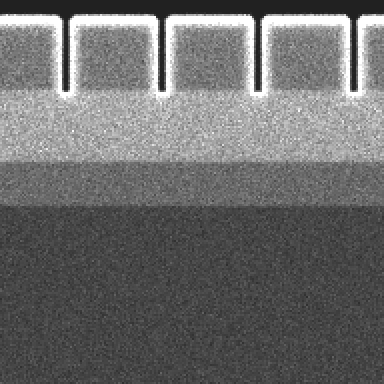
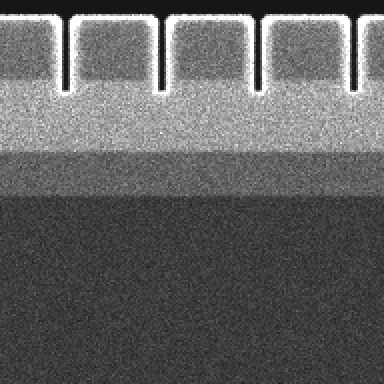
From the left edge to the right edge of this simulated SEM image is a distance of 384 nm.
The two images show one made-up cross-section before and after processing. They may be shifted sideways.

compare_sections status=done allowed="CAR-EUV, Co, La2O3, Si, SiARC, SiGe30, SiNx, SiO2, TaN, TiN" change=removed material="SiO2"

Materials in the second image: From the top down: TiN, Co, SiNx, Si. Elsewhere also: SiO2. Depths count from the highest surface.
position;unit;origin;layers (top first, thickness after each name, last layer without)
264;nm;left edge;empty 2, SiO2 74, Co 60, SiNx 44, Si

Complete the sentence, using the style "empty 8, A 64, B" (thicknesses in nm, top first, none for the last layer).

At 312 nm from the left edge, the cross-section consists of TiN 64, Co 72, SiNx 44, Si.